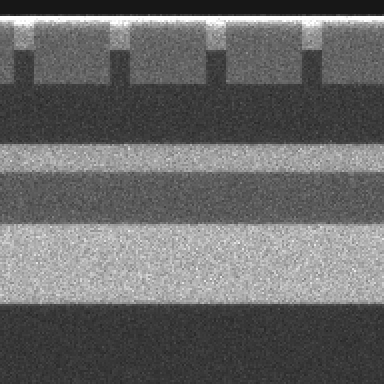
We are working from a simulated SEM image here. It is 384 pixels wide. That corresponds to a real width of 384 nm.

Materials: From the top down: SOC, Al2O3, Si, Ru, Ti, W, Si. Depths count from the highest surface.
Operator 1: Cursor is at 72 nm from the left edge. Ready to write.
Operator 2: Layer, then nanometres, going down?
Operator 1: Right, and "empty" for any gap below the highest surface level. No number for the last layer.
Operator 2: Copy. SOC 68, Si 60, Ru 28, Ti 52, W 80, Si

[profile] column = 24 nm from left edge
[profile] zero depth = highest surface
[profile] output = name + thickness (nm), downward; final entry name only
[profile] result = SOC 6, Al2O3 28, Si 94, Ru 28, Ti 52, W 80, Si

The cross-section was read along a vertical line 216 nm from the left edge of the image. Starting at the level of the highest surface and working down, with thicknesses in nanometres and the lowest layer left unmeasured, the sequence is SOC 6, Al2O3 28, Si 94, Ru 28, Ti 52, W 80, Si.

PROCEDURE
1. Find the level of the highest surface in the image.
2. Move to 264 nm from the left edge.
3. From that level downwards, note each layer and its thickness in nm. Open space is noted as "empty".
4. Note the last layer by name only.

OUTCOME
SOC 68, Si 60, Ru 28, Ti 52, W 80, Si